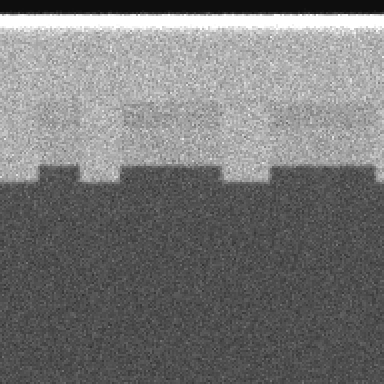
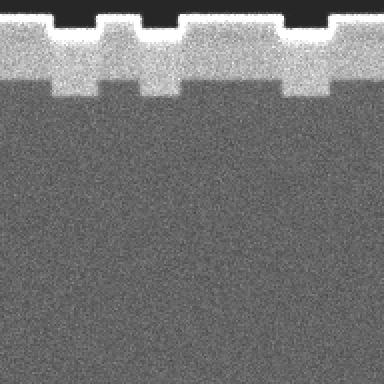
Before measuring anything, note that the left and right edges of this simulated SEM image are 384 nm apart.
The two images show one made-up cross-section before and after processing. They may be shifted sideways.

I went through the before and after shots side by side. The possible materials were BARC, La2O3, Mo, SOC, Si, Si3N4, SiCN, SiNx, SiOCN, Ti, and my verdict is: removed, SOC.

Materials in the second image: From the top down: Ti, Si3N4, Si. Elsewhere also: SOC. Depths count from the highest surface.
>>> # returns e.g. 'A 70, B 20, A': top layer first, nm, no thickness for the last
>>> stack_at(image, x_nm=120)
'Ti 26, Si3N4 38, Si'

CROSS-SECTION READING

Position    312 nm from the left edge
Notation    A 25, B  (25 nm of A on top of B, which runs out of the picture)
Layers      empty 14, SOC 66, Si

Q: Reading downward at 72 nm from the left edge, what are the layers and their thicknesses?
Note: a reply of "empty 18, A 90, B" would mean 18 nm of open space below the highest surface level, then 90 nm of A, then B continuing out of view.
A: empty 14, SOC 66, Si